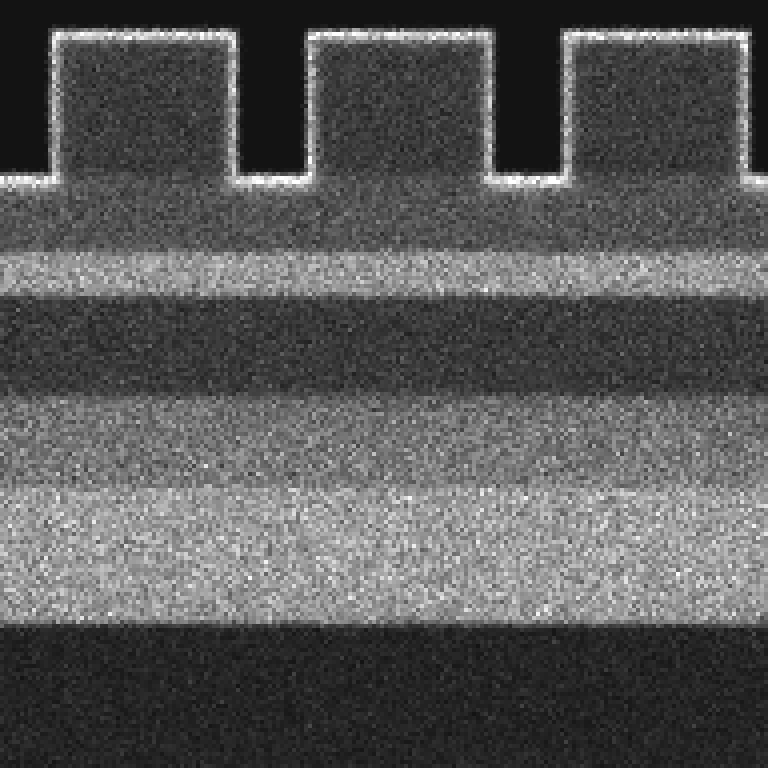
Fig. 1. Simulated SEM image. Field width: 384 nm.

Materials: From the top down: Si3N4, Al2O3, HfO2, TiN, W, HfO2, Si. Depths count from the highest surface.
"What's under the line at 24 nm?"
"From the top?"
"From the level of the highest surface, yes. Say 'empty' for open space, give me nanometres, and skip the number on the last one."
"empty 72, Al2O3 38, HfO2 22, TiN 50, W 46, HfO2 68, Si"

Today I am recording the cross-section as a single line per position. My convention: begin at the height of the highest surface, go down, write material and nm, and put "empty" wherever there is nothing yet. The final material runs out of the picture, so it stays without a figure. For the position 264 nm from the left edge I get empty 72, Al2O3 38, HfO2 22, TiN 50, W 46, HfO2 68, Si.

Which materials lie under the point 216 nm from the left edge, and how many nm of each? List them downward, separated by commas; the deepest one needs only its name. Si3N4 72, Al2O3 38, HfO2 22, TiN 50, W 46, HfO2 68, Si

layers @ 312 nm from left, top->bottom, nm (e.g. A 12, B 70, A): Si3N4 72, Al2O3 38, HfO2 22, TiN 50, W 46, HfO2 68, Si